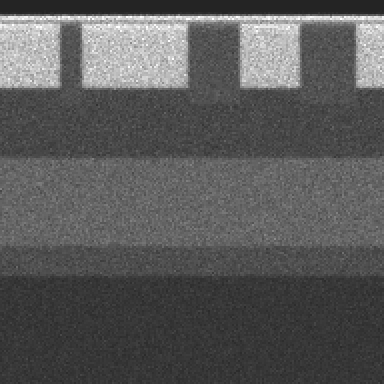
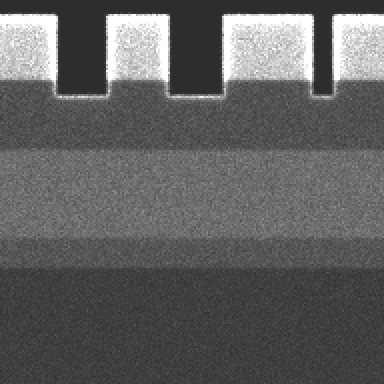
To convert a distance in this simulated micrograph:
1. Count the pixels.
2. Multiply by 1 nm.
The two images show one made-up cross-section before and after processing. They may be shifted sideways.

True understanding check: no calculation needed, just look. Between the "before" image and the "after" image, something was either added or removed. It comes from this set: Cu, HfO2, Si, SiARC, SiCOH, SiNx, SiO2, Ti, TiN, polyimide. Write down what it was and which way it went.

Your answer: SiARC (removed)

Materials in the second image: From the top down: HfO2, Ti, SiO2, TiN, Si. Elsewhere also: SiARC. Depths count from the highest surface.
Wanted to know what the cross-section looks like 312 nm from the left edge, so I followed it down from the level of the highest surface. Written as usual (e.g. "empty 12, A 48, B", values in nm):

empty 80, Ti 54, SiO2 88, TiN 30, Si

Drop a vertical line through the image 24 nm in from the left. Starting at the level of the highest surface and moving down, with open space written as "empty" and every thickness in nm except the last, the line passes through HfO2 64, Ti 70, SiO2 88, TiN 30, Si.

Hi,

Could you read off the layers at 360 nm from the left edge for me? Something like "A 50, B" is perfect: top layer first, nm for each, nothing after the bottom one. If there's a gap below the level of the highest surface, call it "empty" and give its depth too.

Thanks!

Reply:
HfO2 64, Ti 70, SiO2 88, TiN 30, Si